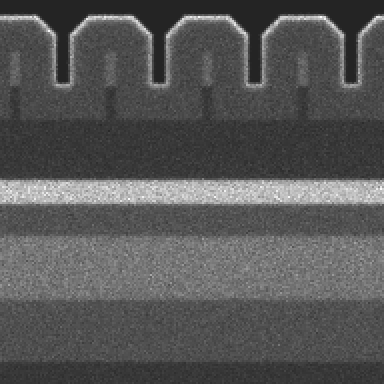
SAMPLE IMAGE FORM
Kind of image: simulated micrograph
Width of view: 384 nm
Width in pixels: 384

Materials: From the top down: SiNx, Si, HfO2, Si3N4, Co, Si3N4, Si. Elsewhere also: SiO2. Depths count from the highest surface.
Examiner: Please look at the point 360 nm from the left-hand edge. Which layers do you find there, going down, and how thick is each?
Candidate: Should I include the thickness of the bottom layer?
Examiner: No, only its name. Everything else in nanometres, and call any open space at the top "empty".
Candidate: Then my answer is empty 16, SiNx 88, Si 60, HfO2 24, Si3N4 32, Co 64, Si3N4 62, Si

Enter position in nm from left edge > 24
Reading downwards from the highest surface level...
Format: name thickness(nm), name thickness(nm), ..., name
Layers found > SiNx 104, Si 60, HfO2 24, Si3N4 32, Co 64, Si3N4 62, Si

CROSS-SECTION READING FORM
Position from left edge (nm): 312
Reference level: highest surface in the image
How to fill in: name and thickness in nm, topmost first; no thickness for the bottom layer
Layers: SiNx 104, Si 60, HfO2 24, Si3N4 32, Co 64, Si3N4 62, Si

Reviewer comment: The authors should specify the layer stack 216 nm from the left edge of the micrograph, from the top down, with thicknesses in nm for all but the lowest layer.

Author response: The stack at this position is SiNx 104, Si 60, HfO2 24, Si3N4 32, Co 64, Si3N4 62, Si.